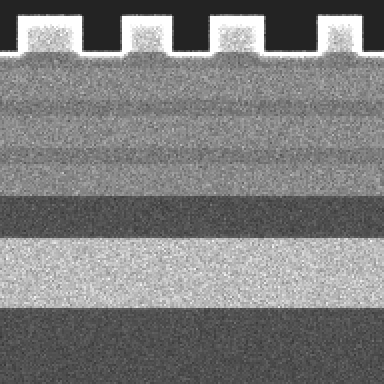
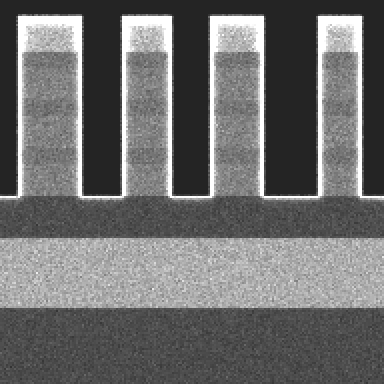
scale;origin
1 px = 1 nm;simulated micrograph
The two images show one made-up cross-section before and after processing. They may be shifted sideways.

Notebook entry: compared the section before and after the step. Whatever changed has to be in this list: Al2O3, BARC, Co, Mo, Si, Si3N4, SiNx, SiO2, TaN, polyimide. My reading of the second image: Si3N4 and SiNx removed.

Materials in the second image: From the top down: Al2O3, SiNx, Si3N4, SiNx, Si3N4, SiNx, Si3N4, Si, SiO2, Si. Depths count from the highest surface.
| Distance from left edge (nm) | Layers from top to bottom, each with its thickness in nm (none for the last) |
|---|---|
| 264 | empty 180, Si 42, SiO2 70, Si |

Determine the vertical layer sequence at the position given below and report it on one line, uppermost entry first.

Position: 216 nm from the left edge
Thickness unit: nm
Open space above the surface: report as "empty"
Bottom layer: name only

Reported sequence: Al2O3 36, SiNx 16, Si3N4 32, SiNx 16, Si3N4 32, SiNx 16, Si3N4 32, Si 42, SiO2 70, Si